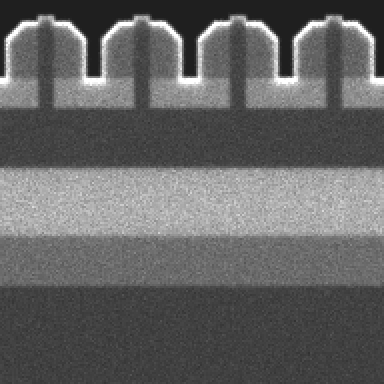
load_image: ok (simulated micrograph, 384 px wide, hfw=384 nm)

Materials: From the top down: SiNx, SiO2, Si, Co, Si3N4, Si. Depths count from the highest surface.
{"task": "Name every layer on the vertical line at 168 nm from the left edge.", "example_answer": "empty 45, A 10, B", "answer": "empty 10, SiNx 52, SiO2 30, Si 60, Co 68, Si3N4 50, Si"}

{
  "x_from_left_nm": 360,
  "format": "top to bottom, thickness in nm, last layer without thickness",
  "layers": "empty 10, SiNx 52, SiO2 30, Si 60, Co 68, Si3N4 50, Si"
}